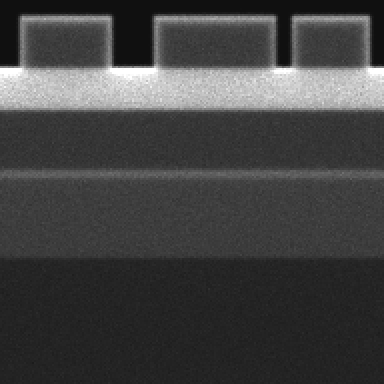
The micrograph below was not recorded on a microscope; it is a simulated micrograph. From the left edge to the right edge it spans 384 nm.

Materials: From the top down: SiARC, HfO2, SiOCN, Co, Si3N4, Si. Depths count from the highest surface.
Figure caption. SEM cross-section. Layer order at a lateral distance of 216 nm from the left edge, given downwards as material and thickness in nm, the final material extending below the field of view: SiARC 52, HfO2 42, SiOCN 60, Co 8, Si3N4 80, Si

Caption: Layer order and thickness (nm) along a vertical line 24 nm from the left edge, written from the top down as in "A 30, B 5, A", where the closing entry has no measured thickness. SiARC 52, HfO2 42, SiOCN 60, Co 8, Si3N4 80, Si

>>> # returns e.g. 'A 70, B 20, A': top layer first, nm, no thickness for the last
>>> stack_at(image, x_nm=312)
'SiARC 52, HfO2 42, SiOCN 60, Co 8, Si3N4 80, Si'